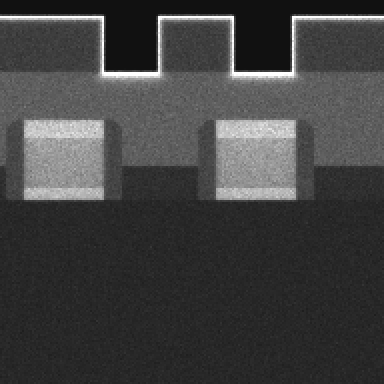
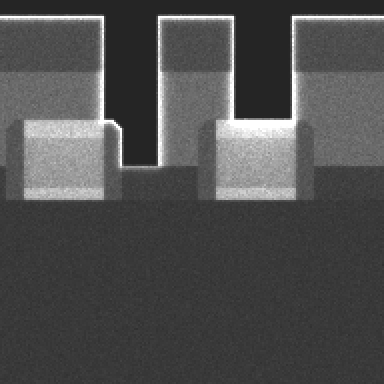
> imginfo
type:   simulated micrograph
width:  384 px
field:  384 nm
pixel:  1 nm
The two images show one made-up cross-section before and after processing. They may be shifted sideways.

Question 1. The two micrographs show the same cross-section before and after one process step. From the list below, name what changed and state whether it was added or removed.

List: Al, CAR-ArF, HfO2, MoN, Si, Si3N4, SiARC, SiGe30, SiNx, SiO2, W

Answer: SiO2, removed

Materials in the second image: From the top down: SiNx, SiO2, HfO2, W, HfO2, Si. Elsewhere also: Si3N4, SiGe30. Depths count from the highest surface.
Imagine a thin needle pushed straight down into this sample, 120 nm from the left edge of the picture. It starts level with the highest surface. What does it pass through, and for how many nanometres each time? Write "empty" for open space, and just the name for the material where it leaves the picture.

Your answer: empty 112, Si3N4 72, Si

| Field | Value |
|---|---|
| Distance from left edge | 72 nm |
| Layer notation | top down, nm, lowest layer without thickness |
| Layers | SiNx 56, SiO2 48, HfO2 18, W 50, HfO2 12, Si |